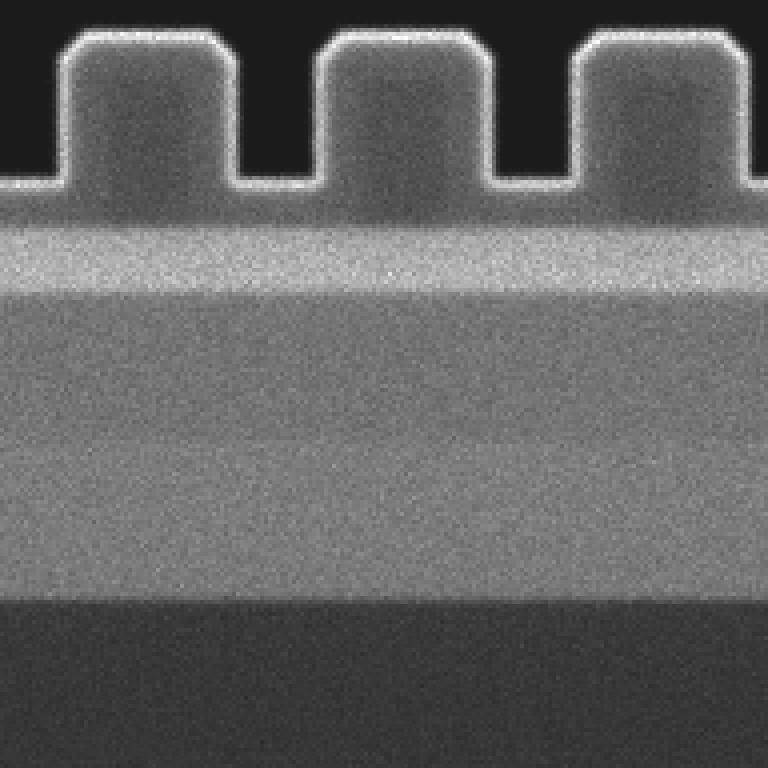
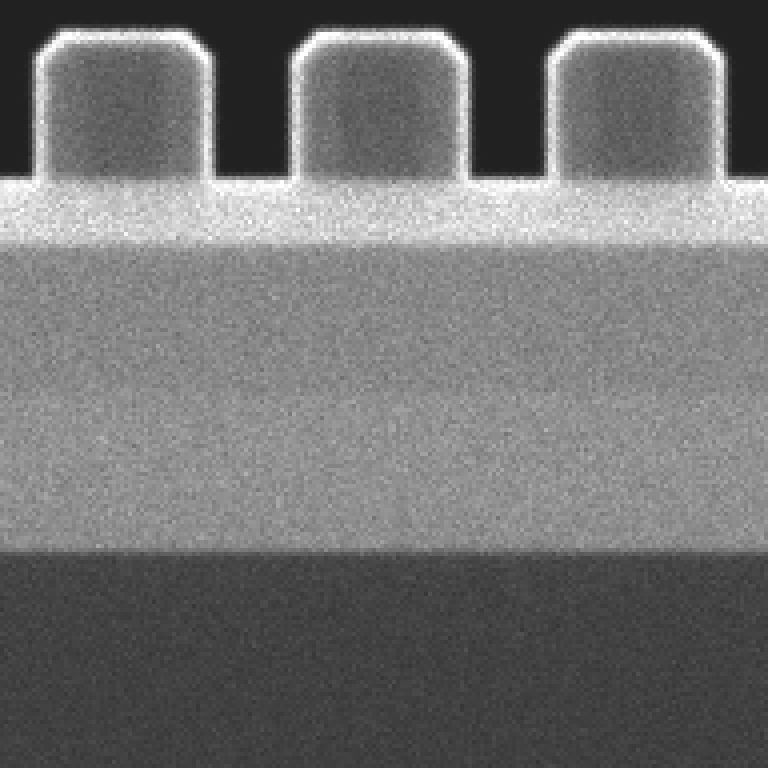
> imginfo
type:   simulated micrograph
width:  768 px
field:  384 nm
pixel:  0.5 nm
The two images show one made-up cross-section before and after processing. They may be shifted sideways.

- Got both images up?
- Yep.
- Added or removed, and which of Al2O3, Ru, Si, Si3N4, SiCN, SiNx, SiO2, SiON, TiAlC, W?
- removed, Si3N4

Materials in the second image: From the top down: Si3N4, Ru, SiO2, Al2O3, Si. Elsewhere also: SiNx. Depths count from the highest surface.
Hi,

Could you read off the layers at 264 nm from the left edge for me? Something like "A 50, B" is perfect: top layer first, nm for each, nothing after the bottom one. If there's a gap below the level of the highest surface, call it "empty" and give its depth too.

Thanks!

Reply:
empty 74, Ru 32, SiO2 74, Al2O3 80, Si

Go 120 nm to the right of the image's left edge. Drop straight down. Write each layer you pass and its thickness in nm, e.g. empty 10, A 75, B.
empty 74, Ru 32, SiO2 74, Al2O3 80, Si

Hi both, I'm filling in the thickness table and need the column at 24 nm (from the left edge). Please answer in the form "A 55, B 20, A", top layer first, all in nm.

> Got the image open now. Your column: empty 6, Si3N4 68, Ru 32, SiO2 74, Al2O3 80, Si